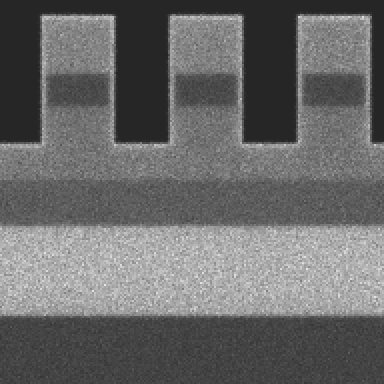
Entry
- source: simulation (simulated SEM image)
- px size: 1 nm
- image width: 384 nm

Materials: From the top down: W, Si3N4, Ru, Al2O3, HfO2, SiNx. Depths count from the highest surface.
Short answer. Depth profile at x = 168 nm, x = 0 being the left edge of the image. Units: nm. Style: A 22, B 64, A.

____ empty 128, Ru 36, Al2O3 46, HfO2 90, SiNx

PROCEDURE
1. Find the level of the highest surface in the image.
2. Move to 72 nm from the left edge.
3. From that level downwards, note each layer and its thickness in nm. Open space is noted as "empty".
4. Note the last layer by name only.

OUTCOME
W 58, Si3N4 32, Ru 74, Al2O3 46, HfO2 90, SiNx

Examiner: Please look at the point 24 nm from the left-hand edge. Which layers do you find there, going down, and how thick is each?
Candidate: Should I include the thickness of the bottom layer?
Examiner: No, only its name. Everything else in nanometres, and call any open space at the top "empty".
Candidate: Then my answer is empty 128, Ru 36, Al2O3 46, HfO2 90, SiNx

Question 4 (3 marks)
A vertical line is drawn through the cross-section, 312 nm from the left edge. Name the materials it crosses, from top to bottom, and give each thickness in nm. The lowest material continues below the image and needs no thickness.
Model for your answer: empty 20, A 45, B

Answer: W 58, Si3N4 32, Ru 74, Al2O3 46, HfO2 90, SiNx